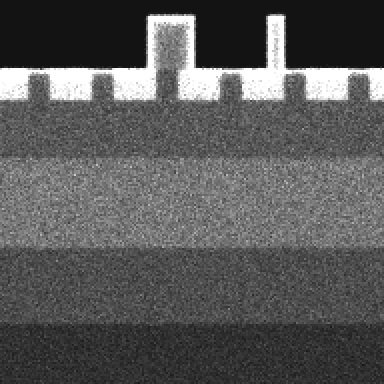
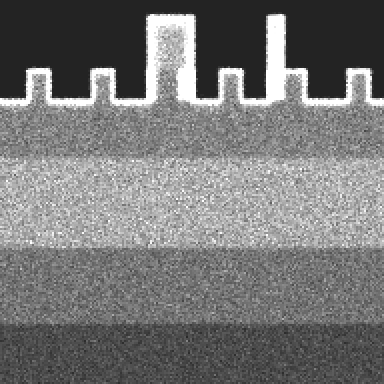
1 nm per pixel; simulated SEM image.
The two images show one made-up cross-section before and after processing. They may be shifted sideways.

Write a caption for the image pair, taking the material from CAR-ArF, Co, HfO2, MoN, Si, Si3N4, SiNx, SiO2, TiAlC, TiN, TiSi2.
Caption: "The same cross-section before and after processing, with HfO2 removed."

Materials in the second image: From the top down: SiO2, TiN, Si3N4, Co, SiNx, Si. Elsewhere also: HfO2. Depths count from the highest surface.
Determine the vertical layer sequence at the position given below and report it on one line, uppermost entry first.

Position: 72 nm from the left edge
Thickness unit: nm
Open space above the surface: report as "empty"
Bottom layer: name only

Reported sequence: empty 84, Si3N4 58, Co 90, SiNx 76, Si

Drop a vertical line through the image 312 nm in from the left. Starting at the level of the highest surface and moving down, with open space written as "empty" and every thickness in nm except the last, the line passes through empty 84, Si3N4 58, Co 90, SiNx 76, Si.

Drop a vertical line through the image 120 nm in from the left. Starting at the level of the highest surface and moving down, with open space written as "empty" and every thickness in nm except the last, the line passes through empty 84, Si3N4 58, Co 90, SiNx 76, Si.